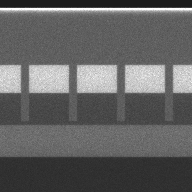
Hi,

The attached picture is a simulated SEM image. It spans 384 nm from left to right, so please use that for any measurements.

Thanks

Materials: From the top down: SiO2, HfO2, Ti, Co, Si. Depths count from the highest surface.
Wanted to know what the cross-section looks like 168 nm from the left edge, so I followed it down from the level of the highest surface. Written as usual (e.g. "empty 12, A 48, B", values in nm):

SiO2 114, HfO2 56, Ti 64, Co 64, Si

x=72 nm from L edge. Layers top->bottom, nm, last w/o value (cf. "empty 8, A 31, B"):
SiO2 114, HfO2 56, Ti 64, Co 64, Si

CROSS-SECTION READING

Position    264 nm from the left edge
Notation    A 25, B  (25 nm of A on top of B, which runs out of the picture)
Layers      SiO2 114, HfO2 56, Ti 64, Co 64, Si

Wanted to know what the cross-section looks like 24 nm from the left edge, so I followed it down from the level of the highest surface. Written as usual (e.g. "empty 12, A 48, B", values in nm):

SiO2 114, HfO2 56, Ti 64, Co 64, Si